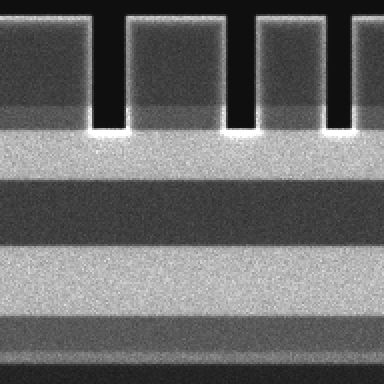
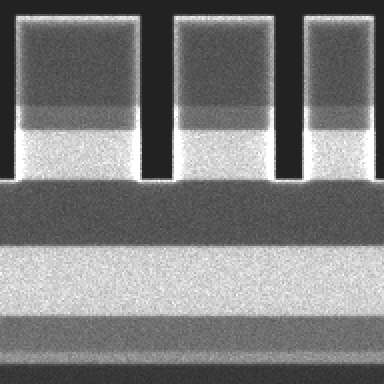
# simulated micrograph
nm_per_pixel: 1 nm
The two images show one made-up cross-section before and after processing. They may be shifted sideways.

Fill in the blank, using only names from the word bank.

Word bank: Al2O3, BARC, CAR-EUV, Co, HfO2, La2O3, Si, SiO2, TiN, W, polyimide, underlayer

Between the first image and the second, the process removed HfO2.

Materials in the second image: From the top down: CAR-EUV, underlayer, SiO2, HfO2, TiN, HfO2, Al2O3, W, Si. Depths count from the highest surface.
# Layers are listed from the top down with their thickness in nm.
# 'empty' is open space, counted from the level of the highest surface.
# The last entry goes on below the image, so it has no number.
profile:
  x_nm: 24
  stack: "CAR-EUV 64, underlayer 26, SiO2 24, HfO2 50, TiN 66, HfO2 70, Al2O3 36, W 12, Si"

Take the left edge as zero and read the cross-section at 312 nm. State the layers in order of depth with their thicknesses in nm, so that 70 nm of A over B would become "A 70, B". CAR-EUV 64, underlayer 26, SiO2 24, HfO2 50, TiN 66, HfO2 70, Al2O3 36, W 12, Si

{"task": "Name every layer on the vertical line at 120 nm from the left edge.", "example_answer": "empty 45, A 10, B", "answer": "CAR-EUV 64, underlayer 26, SiO2 24, HfO2 50, TiN 66, HfO2 70, Al2O3 36, W 12, Si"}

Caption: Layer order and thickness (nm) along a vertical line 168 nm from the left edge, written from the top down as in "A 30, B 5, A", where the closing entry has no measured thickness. empty 164, TiN 66, HfO2 70, Al2O3 36, W 12, Si